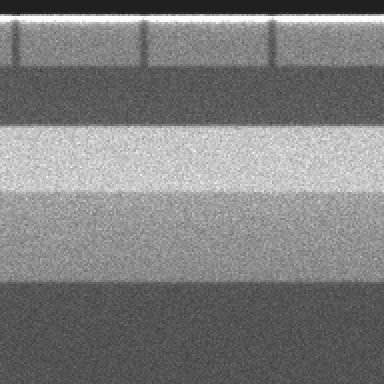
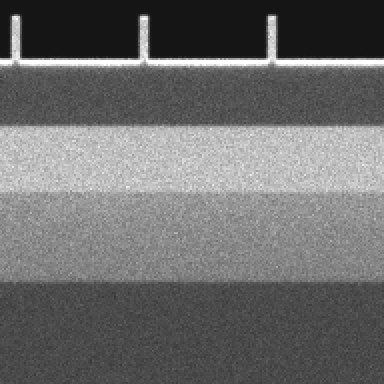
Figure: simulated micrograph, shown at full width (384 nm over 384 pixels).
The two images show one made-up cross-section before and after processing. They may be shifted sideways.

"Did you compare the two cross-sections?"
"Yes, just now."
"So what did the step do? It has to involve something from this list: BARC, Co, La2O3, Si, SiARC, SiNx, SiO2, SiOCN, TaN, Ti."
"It removed SiNx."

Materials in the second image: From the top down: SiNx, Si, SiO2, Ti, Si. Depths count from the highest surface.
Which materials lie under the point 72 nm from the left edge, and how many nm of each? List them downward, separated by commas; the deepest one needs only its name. empty 44, SiNx 6, Si 60, SiO2 66, Ti 90, Si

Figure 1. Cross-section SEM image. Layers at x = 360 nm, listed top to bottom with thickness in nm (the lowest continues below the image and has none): empty 44, SiNx 6, Si 60, SiO2 66, Ti 90, Si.